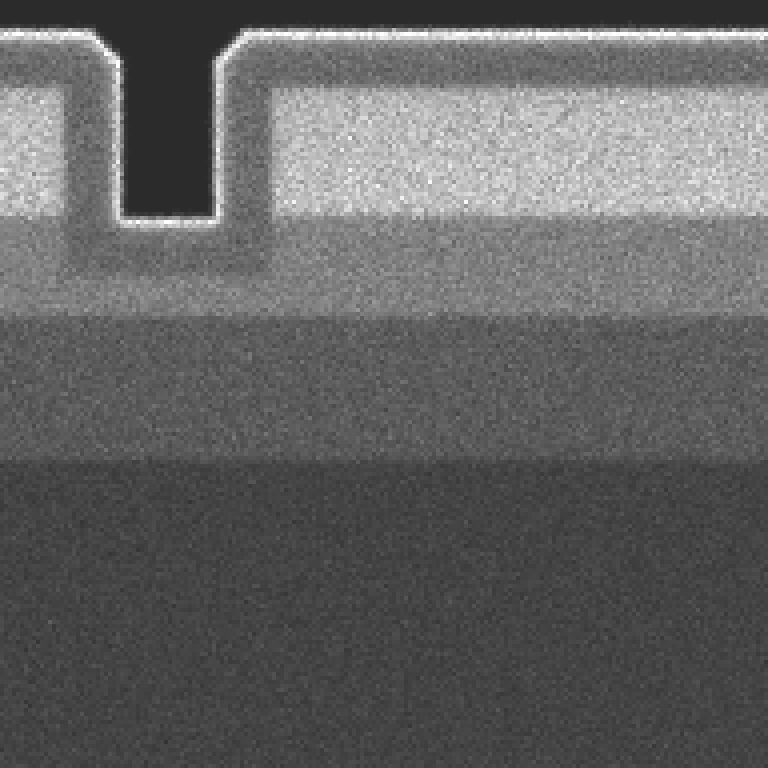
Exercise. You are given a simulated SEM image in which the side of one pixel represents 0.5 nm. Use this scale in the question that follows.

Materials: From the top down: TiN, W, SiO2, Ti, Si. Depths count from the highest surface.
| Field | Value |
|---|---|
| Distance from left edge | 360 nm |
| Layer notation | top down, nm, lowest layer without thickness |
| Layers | TiN 28, W 64, SiO2 50, Ti 72, Si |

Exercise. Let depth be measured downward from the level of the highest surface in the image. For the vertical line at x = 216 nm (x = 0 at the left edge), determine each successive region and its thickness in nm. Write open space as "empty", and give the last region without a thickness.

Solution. TiN 28, W 64, SiO2 50, Ti 72, Si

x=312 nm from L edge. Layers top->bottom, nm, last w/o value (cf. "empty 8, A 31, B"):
TiN 28, W 64, SiO2 50, Ti 72, Si